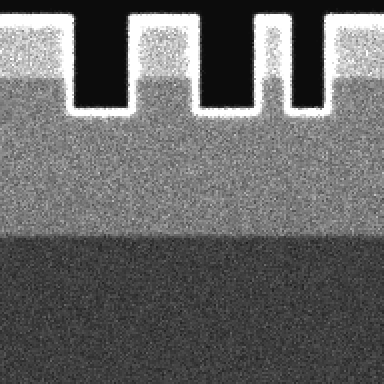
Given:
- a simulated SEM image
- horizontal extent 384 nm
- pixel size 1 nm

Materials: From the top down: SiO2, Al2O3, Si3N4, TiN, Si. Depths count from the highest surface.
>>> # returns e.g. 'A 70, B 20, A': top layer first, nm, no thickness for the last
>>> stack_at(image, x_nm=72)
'empty 94, Si3N4 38, TiN 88, Si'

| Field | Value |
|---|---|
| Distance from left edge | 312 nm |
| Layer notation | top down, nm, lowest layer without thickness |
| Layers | empty 94, Si3N4 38, TiN 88, Si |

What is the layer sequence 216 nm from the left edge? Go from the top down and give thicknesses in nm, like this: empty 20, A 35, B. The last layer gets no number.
empty 94, Si3N4 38, TiN 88, Si